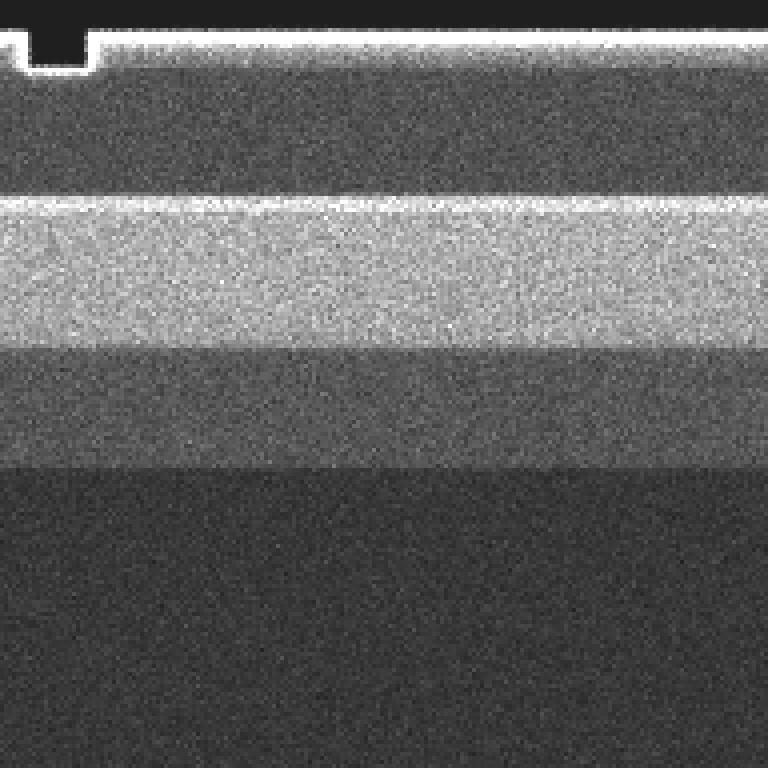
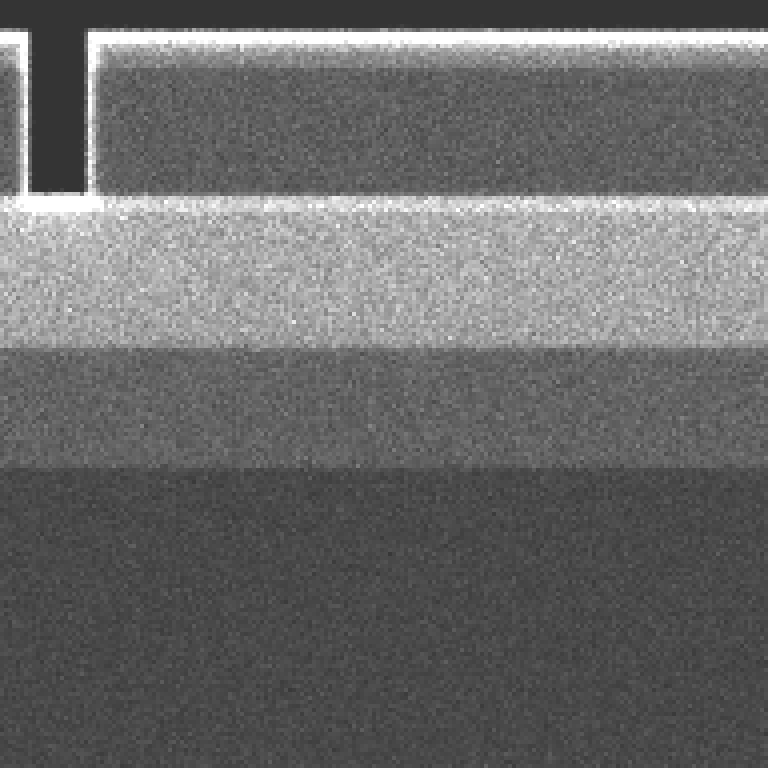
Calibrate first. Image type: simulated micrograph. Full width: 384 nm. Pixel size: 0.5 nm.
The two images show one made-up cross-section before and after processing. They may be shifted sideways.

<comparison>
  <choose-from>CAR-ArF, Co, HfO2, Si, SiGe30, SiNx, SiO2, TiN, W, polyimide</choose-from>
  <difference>SiNx removed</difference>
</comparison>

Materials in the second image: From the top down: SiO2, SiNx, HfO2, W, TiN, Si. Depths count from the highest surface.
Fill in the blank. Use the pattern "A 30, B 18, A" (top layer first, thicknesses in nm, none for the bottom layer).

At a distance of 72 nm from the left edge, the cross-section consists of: SiO2 18, SiNx 64, HfO2 8, W 68, TiN 60, Si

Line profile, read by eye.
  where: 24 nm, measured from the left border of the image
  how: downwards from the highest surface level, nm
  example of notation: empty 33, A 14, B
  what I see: empty 82, HfO2 8, W 68, TiN 60, Si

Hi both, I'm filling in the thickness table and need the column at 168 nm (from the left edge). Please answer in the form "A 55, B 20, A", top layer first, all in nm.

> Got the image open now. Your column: SiO2 18, SiNx 64, HfO2 8, W 68, TiN 60, Si